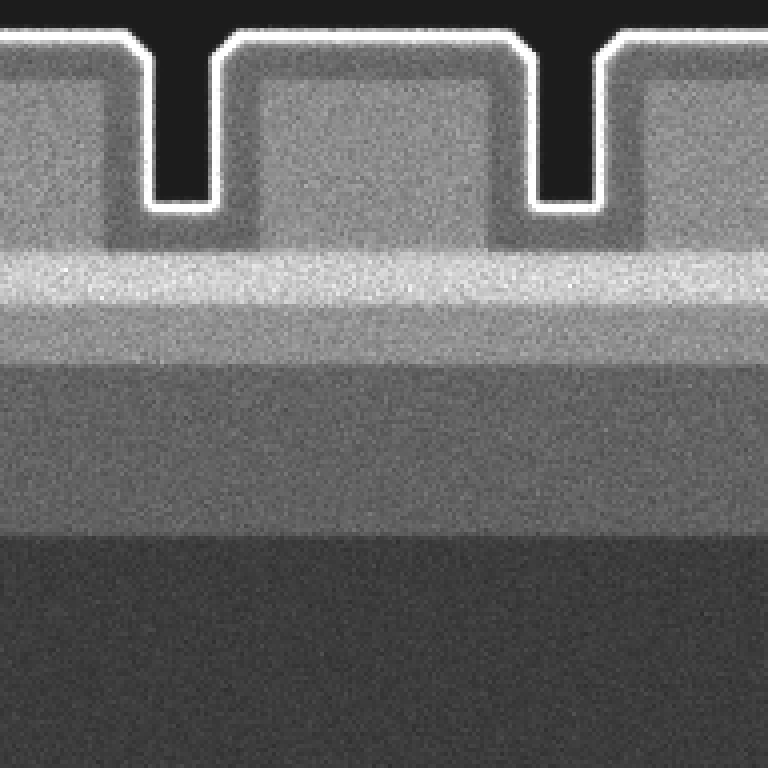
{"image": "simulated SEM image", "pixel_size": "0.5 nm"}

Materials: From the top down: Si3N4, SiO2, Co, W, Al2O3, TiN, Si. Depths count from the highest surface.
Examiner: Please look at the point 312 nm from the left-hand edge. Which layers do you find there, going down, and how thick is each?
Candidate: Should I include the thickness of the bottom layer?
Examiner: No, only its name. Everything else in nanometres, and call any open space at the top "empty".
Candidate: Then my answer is Si3N4 110, W 26, Al2O3 30, TiN 86, Si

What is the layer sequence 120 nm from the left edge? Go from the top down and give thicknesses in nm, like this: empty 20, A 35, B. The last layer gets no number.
Si3N4 110, W 26, Al2O3 30, TiN 86, Si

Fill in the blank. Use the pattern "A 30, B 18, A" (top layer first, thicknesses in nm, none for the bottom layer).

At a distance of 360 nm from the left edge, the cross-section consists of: Si3N4 24, SiO2 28, Co 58, W 26, Al2O3 30, TiN 86, Si